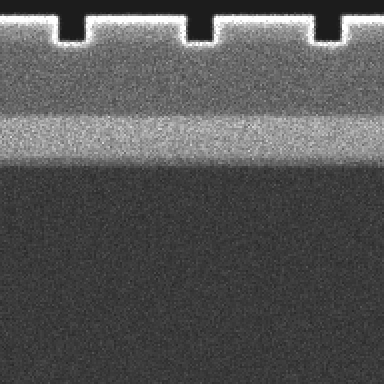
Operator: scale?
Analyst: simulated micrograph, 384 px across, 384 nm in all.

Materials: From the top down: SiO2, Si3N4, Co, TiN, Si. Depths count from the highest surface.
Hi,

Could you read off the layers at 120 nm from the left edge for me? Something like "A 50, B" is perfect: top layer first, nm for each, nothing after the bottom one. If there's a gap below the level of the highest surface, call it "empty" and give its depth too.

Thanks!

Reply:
SiO2 26, Si3N4 74, Co 42, TiN 8, Si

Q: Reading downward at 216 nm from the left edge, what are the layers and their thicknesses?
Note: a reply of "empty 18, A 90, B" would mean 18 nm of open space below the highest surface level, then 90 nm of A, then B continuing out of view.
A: SiO2 26, Si3N4 74, Co 42, TiN 8, Si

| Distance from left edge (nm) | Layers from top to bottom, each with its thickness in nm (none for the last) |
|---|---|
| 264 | SiO2 26, Si3N4 74, Co 42, TiN 8, Si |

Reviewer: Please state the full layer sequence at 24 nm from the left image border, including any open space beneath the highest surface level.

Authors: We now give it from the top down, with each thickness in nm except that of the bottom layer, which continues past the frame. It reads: SiO2 26, Si3N4 74, Co 42, TiN 8, Si